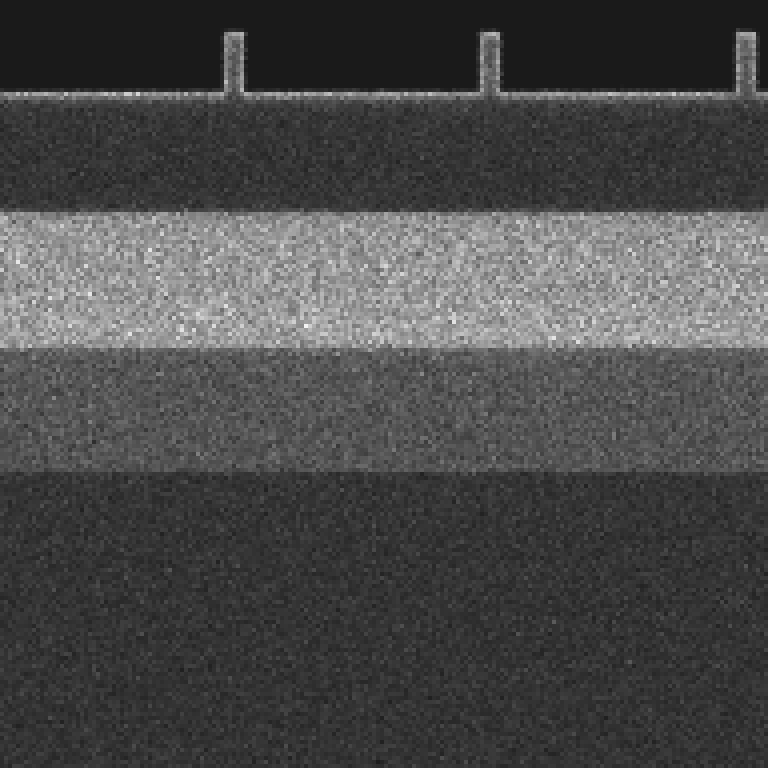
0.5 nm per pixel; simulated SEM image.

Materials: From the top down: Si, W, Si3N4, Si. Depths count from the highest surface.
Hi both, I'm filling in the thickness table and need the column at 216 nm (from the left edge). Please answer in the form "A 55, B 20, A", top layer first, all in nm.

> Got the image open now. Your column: empty 30, Si 60, W 68, Si3N4 62, Si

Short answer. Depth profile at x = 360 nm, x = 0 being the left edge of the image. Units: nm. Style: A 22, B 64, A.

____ empty 30, Si 60, W 68, Si3N4 62, Si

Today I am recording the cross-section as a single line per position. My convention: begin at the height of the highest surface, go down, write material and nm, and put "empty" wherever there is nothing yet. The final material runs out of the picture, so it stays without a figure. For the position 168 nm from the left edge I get empty 30, Si 60, W 68, Si3N4 62, Si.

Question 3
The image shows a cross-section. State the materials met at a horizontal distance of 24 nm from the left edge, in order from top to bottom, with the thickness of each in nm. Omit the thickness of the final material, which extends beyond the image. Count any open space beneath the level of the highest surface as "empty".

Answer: empty 30, Si 60, W 68, Si3N4 62, Si